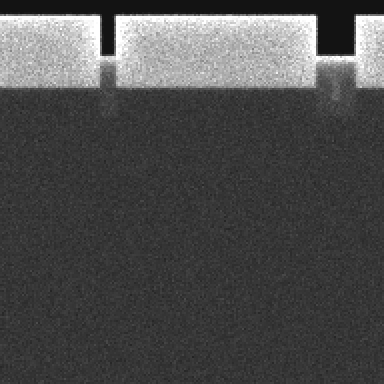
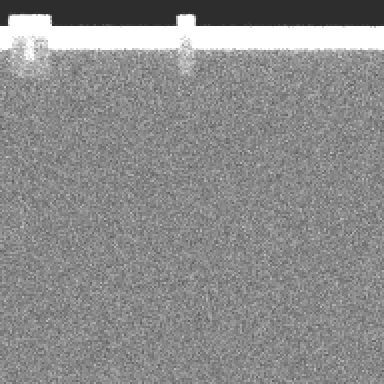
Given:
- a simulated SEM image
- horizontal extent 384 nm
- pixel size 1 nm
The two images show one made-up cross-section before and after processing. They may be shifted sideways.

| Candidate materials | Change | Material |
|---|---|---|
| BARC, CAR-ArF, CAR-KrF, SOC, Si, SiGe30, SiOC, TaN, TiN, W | removed | W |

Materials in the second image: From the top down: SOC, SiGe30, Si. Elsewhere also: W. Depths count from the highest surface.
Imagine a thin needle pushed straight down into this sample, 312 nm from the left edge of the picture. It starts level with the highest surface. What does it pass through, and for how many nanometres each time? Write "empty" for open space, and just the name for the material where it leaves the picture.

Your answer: empty 12, W 20, Si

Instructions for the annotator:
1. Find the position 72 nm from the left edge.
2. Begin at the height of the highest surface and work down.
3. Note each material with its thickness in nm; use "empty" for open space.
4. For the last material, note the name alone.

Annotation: empty 12, W 20, Si